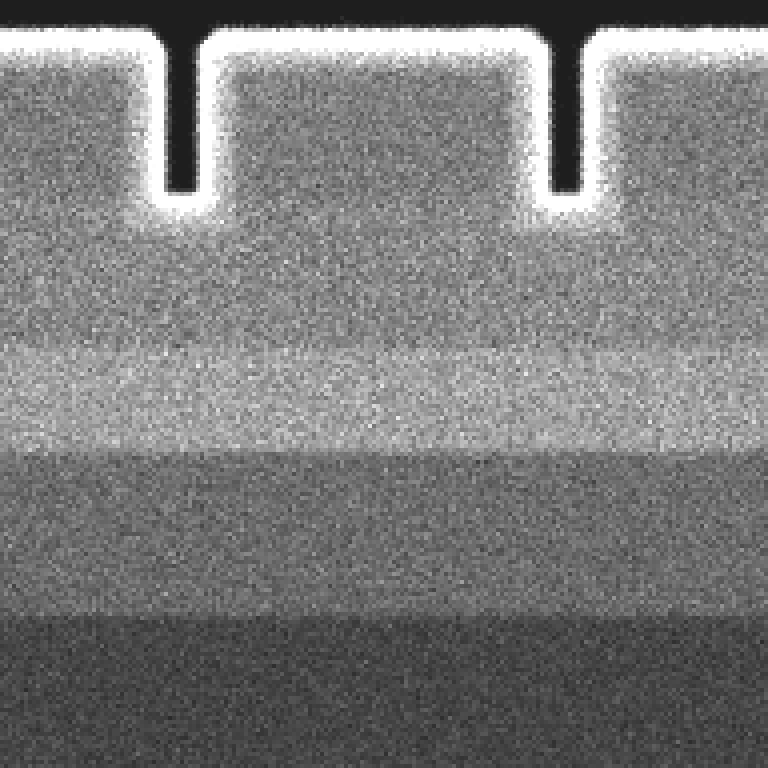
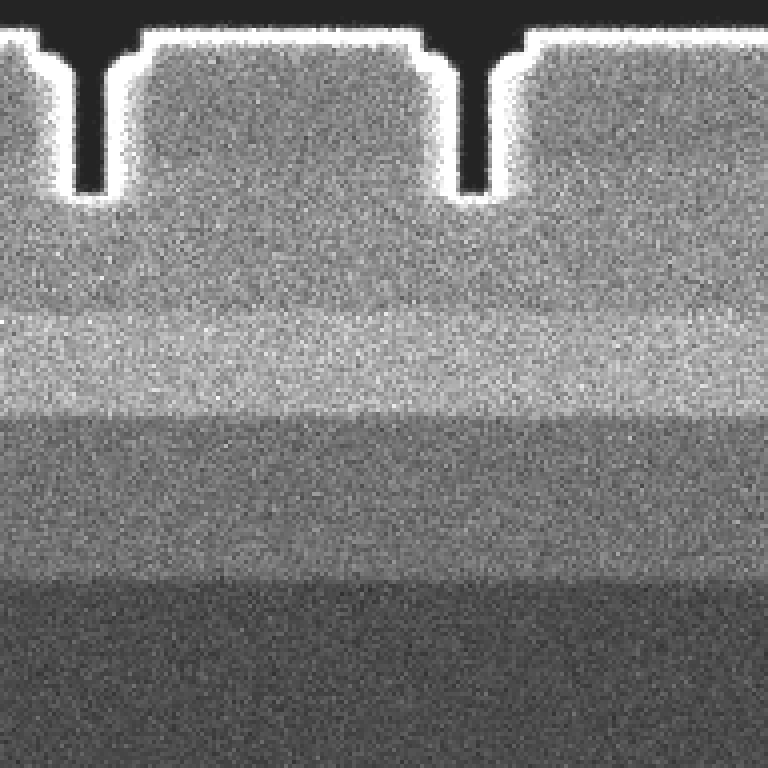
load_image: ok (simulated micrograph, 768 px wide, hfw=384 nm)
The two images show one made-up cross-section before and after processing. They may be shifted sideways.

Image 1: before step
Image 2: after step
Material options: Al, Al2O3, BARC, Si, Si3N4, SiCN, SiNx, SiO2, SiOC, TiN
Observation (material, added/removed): Al2O3, removed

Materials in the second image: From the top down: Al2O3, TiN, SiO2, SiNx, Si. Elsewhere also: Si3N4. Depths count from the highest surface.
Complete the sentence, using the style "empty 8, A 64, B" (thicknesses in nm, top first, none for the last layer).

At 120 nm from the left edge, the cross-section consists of Si3N4 64, TiN 76, SiO2 52, SiNx 82, Si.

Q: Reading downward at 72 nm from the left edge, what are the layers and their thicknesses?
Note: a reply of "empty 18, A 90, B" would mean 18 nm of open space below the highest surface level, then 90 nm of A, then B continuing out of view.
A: Si3N4 64, TiN 76, SiO2 52, SiNx 82, Si